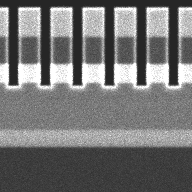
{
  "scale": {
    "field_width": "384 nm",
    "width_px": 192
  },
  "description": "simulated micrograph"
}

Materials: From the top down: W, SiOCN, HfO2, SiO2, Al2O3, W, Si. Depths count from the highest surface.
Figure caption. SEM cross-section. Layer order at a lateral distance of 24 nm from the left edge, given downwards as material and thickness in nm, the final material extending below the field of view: empty 156, SiO2 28, Al2O3 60, W 34, Si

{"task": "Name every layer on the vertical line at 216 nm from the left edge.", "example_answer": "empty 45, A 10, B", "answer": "empty 156, SiO2 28, Al2O3 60, W 34, Si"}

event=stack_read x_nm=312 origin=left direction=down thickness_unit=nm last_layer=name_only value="W 58, SiOCN 54, HfO2 38, SiO2 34, Al2O3 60, W 34, Si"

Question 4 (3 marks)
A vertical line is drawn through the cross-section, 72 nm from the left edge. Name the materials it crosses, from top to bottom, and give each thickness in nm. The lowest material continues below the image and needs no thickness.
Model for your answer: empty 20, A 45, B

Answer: W 58, SiOCN 54, HfO2 38, SiO2 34, Al2O3 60, W 34, Si